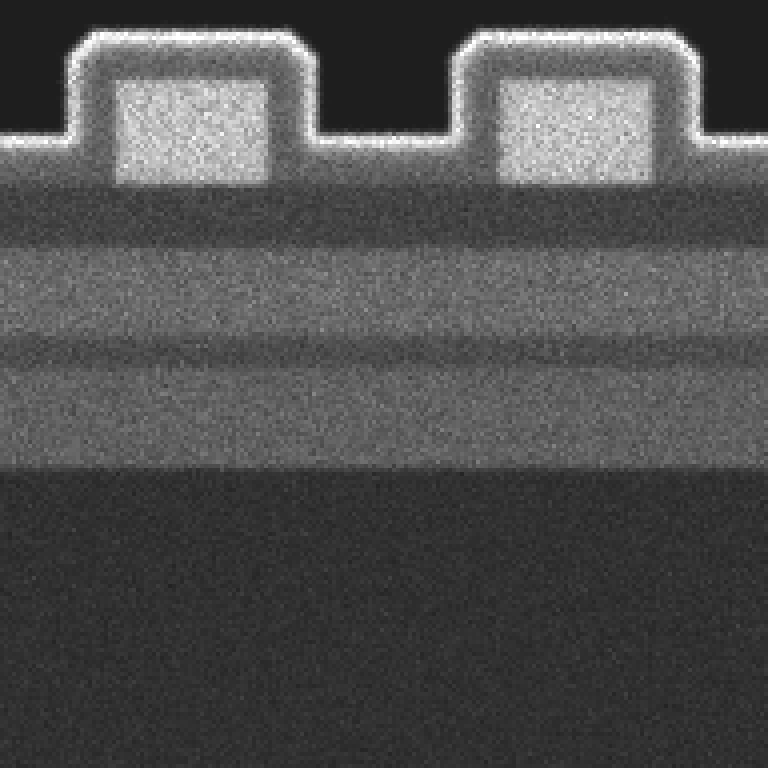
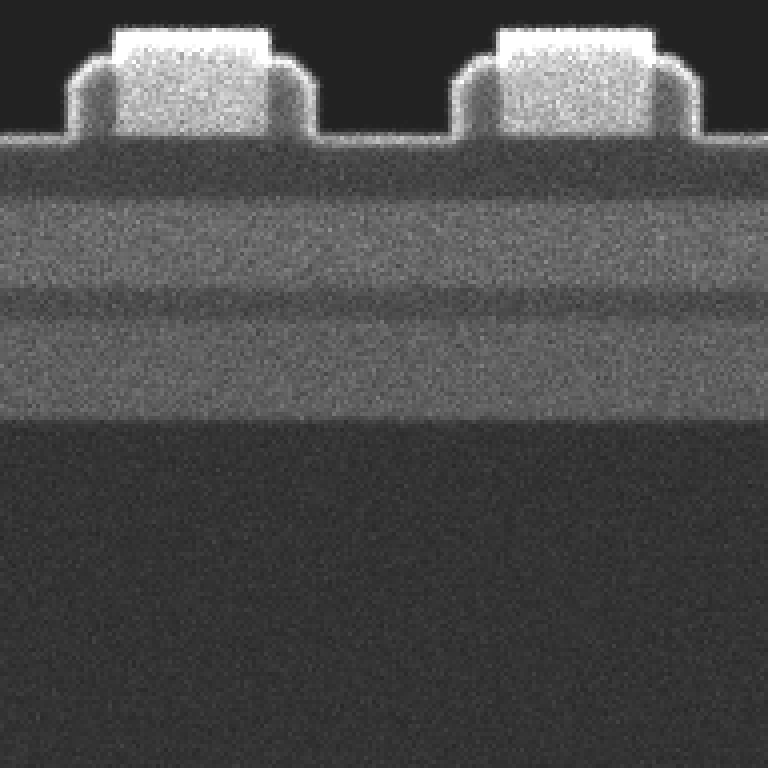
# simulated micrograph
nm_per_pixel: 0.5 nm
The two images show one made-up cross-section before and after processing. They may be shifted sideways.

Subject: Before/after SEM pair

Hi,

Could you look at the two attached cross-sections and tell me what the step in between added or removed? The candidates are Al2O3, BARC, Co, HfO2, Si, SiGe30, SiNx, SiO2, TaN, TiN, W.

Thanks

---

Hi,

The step removed SiO2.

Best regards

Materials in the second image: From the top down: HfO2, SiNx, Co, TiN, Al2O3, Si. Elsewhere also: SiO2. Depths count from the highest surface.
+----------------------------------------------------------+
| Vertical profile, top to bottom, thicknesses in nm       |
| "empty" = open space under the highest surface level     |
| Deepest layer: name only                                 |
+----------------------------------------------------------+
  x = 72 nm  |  HfO2 52, SiNx 32, Co 44, TiN 16, Al2O3 50, Si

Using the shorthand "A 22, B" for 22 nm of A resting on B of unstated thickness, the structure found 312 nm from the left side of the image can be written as HfO2 52, SiNx 32, Co 44, TiN 16, Al2O3 50, Si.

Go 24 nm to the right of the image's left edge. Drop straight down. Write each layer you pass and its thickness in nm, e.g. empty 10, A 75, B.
empty 52, SiNx 32, Co 44, TiN 16, Al2O3 50, Si